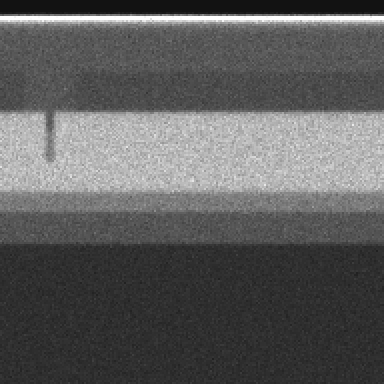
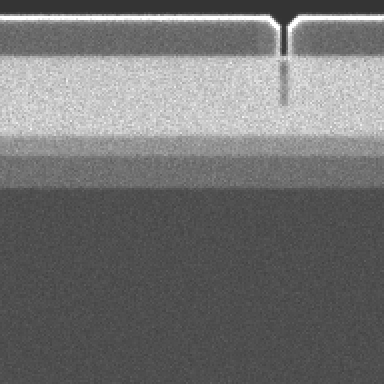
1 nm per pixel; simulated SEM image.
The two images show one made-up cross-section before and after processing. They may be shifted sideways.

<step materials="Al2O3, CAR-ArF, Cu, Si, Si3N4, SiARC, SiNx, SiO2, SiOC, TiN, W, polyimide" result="removed SiARC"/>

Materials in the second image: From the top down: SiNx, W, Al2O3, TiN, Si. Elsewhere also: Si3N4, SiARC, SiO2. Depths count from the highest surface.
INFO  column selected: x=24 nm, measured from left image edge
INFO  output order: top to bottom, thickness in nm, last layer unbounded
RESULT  SiNx 40, W 80, Al2O3 20, TiN 32, Si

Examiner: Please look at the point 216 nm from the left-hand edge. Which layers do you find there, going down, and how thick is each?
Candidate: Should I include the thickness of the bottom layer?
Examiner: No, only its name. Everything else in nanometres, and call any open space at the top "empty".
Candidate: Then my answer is SiNx 40, W 80, Al2O3 20, TiN 32, Si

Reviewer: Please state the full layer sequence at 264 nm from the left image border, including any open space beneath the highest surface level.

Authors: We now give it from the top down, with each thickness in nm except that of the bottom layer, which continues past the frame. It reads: Si3N4 40, W 80, Al2O3 20, TiN 32, Si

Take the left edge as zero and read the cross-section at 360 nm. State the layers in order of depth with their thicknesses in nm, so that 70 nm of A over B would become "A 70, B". SiNx 40, W 80, Al2O3 20, TiN 32, Si